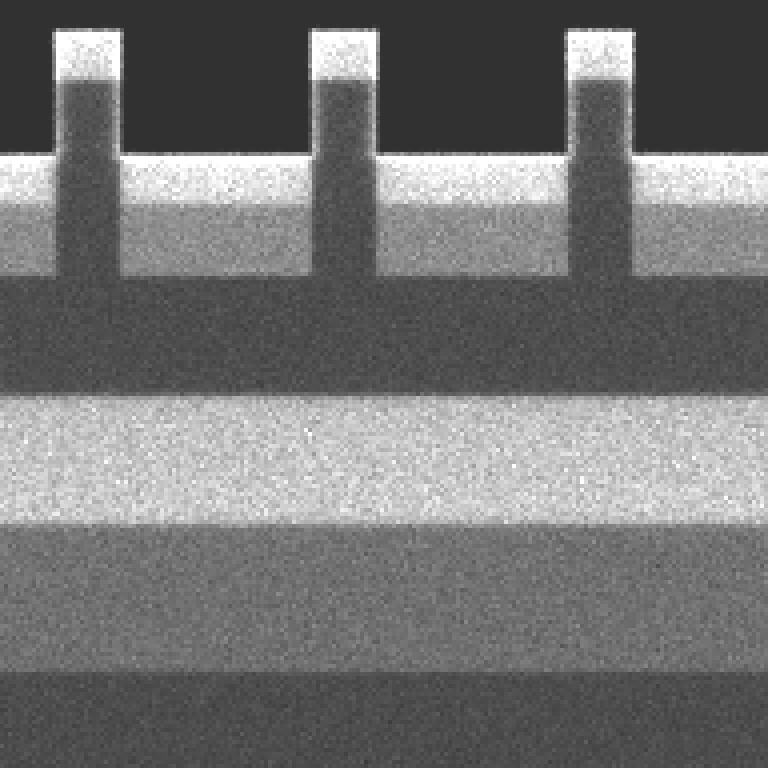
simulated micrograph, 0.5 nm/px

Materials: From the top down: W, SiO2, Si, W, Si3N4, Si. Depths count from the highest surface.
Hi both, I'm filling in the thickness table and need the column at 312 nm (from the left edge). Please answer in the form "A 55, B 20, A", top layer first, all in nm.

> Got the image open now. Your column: W 24, Si 158, W 64, Si3N4 74, Si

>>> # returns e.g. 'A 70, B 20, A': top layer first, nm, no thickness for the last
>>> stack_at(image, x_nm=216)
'empty 62, W 24, SiO2 36, Si 60, W 64, Si3N4 74, Si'